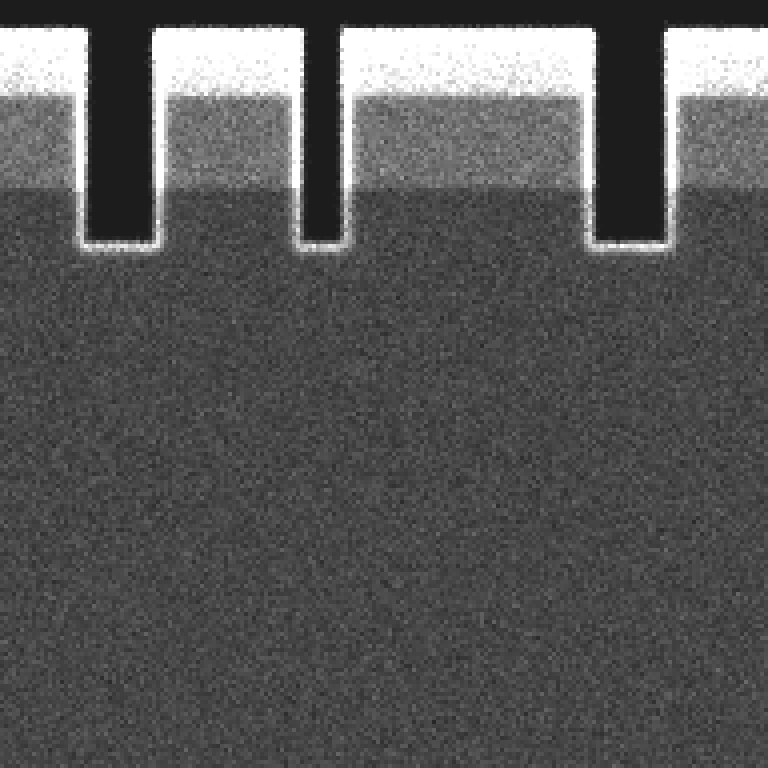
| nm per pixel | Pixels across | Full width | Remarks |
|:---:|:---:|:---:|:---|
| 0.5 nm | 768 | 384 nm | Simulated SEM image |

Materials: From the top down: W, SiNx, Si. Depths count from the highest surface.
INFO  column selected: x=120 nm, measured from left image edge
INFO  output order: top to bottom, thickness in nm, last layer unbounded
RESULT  W 32, SiNx 46, Si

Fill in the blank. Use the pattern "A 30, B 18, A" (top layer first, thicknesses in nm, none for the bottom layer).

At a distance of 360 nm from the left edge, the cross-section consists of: W 32, SiNx 46, Si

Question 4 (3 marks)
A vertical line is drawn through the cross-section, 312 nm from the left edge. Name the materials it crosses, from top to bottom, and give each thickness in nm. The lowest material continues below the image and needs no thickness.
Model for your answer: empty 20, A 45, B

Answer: empty 106, Si